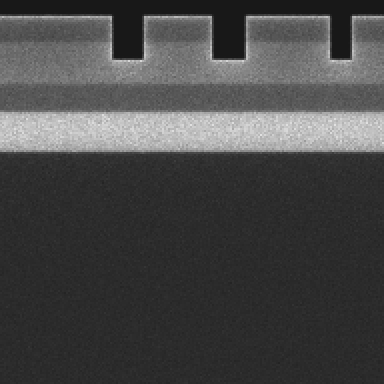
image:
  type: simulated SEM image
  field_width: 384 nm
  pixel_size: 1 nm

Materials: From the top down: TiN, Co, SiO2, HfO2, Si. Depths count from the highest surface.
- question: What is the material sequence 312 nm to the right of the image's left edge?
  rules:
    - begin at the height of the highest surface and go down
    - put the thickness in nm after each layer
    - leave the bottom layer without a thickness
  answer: TiN 26, Co 42, SiO2 28, HfO2 40, Si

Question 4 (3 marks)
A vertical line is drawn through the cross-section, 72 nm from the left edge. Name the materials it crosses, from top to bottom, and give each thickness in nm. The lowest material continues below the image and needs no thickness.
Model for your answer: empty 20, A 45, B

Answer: TiN 26, Co 42, SiO2 28, HfO2 40, Si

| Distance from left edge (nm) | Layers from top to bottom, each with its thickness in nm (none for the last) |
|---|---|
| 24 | TiN 26, Co 42, SiO2 28, HfO2 40, Si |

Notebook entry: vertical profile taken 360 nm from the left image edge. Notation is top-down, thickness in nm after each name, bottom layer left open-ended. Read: TiN 26, Co 42, SiO2 28, HfO2 40, Si